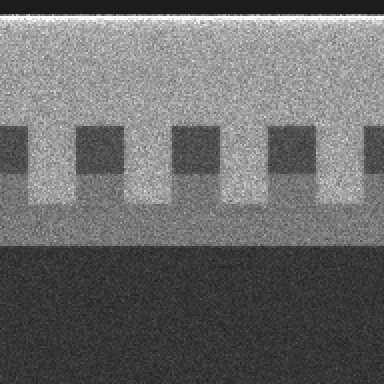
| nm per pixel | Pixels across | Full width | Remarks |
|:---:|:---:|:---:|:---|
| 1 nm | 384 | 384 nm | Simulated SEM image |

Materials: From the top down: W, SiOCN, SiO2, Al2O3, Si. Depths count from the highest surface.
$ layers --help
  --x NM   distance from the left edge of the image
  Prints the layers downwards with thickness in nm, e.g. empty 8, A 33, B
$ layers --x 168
W 188, SiO2 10, Al2O3 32, Si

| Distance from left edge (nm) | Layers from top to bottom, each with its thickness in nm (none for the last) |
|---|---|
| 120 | W 110, SiOCN 48, SiO2 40, Al2O3 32, Si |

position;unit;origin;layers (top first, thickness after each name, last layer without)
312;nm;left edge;W 110, SiOCN 48, SiO2 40, Al2O3 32, Si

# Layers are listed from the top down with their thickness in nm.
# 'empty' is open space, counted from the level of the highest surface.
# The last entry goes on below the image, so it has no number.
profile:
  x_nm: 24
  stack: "W 110, SiOCN 48, SiO2 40, Al2O3 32, Si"